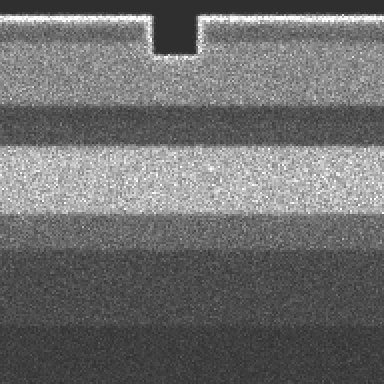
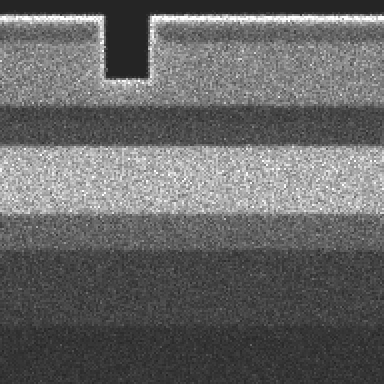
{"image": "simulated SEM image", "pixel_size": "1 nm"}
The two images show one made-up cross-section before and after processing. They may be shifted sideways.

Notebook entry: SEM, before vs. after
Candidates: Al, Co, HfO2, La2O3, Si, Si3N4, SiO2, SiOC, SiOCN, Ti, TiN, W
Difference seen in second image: W removed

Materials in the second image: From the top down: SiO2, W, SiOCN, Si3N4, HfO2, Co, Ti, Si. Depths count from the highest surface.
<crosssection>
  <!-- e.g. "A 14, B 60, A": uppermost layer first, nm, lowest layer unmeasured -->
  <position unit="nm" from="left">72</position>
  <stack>SiO2 26, W 64, SiOCN 16, Si3N4 24, HfO2 68, Co 36, Ti 76, Si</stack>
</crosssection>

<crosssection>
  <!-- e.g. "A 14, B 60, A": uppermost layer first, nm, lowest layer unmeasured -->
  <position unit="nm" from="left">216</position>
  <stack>SiO2 26, W 64, SiOCN 16, Si3N4 24, HfO2 68, Co 36, Ti 76, Si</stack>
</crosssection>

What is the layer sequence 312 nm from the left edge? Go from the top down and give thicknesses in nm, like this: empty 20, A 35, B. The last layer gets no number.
SiO2 26, W 64, SiOCN 16, Si3N4 24, HfO2 68, Co 36, Ti 76, Si